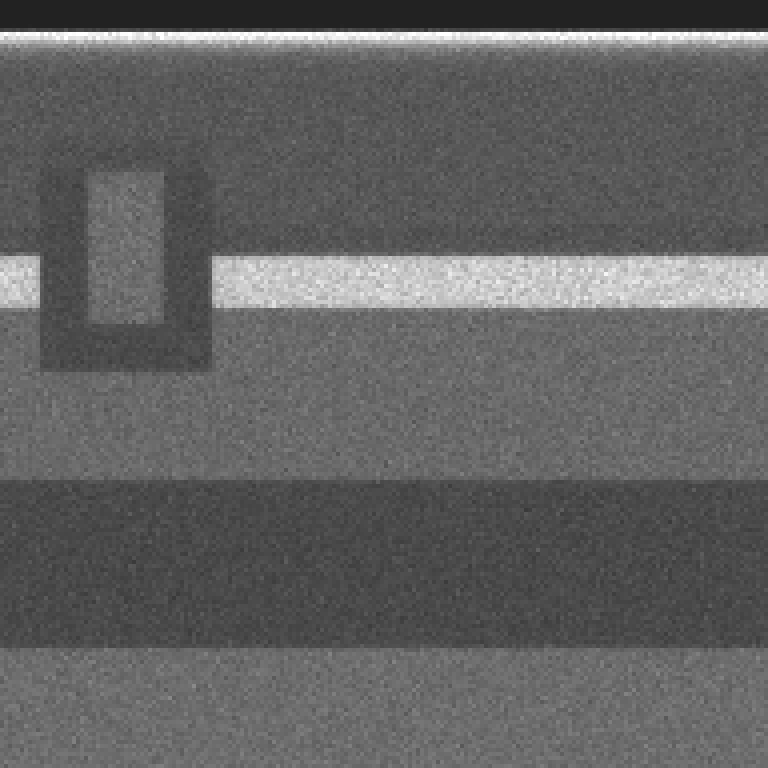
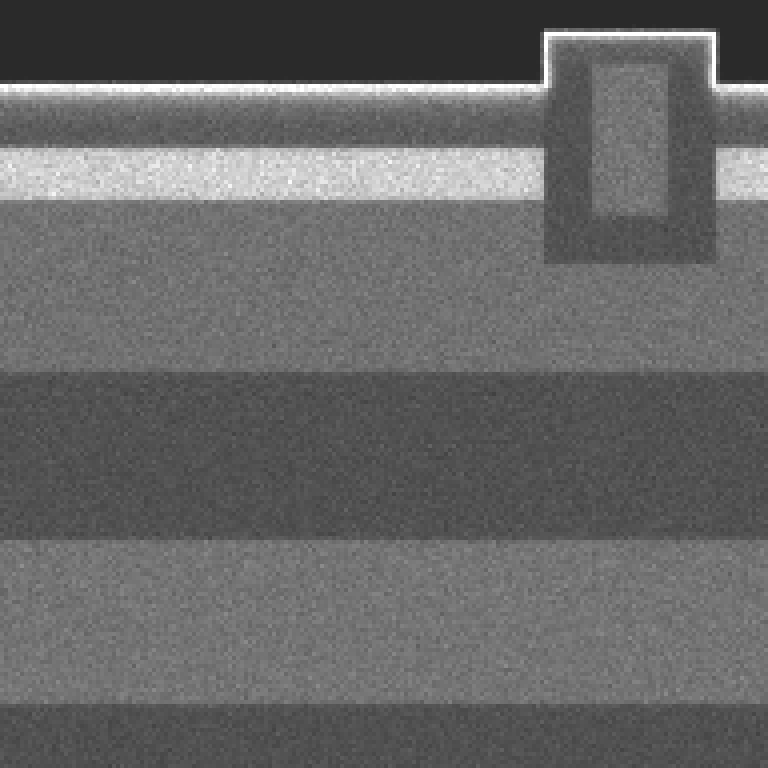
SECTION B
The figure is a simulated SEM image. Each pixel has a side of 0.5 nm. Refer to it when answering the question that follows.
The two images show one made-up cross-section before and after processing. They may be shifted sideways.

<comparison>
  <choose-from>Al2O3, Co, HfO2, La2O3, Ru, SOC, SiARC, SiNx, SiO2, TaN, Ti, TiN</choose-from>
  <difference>SOC removed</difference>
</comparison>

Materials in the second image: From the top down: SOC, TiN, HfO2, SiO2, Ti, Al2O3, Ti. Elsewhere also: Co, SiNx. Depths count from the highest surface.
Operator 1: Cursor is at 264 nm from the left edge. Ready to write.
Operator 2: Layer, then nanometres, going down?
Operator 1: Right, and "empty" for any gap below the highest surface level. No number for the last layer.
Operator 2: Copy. empty 26, SOC 16, TiN 16, HfO2 26, SiO2 86, Ti 84, Al2O3 82, Ti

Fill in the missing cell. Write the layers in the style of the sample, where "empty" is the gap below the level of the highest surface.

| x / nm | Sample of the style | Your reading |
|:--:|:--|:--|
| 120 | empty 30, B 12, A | empty 26, SOC 16, TiN 16, HfO2 26, SiO2 86, Ti 84, Al2O3 82, Ti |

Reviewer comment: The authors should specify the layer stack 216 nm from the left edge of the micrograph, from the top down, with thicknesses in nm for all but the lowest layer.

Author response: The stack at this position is empty 26, SOC 16, TiN 16, HfO2 26, SiO2 86, Ti 84, Al2O3 82, Ti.